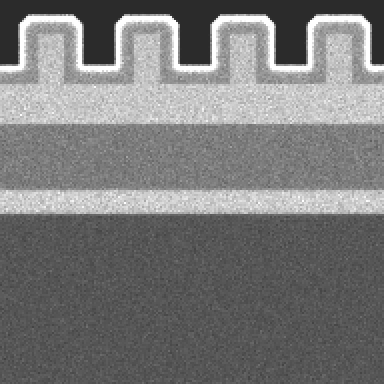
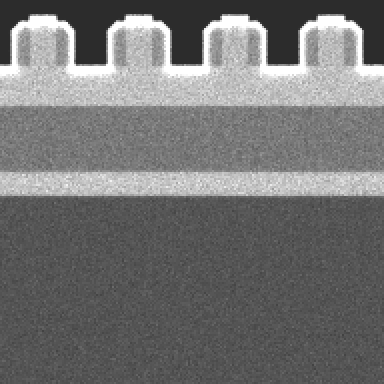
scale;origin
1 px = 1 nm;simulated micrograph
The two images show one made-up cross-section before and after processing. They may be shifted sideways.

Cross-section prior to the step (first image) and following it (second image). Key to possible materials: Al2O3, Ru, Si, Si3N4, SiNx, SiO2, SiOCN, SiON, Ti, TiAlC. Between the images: Si3N4 was removed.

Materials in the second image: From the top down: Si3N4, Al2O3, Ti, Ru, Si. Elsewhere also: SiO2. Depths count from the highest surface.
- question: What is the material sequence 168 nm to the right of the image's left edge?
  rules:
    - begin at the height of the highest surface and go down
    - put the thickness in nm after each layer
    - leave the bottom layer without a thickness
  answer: empty 14, Si3N4 36, Al2O3 40, Ti 66, Ru 24, Si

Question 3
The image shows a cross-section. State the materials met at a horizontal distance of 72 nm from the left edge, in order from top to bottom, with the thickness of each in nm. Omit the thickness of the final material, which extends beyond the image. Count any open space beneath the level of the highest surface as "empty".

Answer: empty 14, Si3N4 36, Al2O3 40, Ti 66, Ru 24, Si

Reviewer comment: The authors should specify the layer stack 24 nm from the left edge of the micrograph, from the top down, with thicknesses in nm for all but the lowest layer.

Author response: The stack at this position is empty 6, Si3N4 44, Al2O3 40, Ti 66, Ru 24, Si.